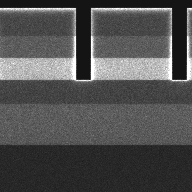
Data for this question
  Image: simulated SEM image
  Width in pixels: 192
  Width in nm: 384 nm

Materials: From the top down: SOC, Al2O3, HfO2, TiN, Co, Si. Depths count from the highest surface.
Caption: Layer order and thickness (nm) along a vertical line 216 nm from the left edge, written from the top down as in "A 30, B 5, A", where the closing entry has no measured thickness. SOC 56, Al2O3 44, HfO2 44, TiN 48, Co 82, Si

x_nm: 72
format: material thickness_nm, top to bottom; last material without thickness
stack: SOC 56, Al2O3 44, HfO2 44, TiN 48, Co 82, Si